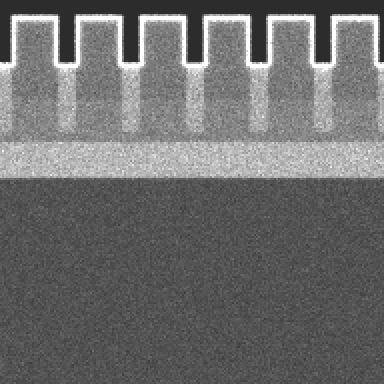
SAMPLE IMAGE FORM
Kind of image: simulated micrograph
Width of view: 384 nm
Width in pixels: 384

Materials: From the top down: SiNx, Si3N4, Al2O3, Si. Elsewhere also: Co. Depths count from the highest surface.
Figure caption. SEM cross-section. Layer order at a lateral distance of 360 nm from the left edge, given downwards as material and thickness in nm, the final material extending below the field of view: SiNx 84, Si3N4 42, Al2O3 36, Si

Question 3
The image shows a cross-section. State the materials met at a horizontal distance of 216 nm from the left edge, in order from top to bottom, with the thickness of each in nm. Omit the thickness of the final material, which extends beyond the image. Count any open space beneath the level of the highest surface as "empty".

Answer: SiNx 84, Si3N4 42, Al2O3 36, Si